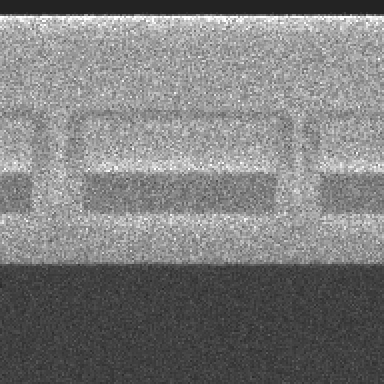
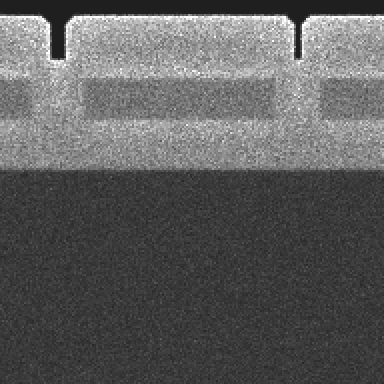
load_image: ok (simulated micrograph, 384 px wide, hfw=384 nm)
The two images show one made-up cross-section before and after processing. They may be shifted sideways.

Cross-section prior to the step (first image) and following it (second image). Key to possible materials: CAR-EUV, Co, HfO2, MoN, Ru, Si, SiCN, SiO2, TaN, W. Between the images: W was removed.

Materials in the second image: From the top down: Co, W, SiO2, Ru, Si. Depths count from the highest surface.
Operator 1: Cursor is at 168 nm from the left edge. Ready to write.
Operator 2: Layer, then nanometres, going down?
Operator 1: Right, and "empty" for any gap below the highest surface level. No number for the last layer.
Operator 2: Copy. Co 10, W 52, SiO2 42, Ru 50, Si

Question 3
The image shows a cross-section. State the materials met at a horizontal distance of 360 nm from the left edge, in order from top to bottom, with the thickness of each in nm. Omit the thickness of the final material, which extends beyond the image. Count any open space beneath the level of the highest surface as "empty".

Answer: Co 10, W 52, SiO2 42, Ru 50, Si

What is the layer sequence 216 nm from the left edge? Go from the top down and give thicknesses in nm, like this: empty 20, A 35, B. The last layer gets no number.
Co 10, W 52, SiO2 42, Ru 50, Si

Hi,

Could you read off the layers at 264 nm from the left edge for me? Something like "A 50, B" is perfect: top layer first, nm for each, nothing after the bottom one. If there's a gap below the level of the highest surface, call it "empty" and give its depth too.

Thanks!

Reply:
Co 10, W 52, SiO2 42, Ru 50, Si